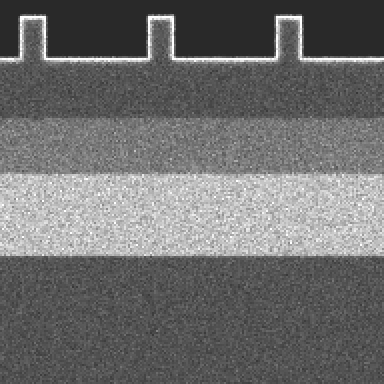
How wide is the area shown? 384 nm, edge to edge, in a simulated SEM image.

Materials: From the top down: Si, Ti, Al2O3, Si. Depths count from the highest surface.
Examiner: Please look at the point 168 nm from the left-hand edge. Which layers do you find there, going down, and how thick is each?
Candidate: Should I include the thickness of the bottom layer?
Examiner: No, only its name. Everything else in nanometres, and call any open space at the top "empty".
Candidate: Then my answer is Si 102, Ti 56, Al2O3 82, Si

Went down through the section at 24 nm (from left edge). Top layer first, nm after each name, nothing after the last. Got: Si 102, Ti 56, Al2O3 82, Si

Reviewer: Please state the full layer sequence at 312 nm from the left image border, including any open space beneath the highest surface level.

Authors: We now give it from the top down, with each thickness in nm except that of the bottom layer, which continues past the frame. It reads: empty 42, Si 60, Ti 56, Al2O3 82, Si